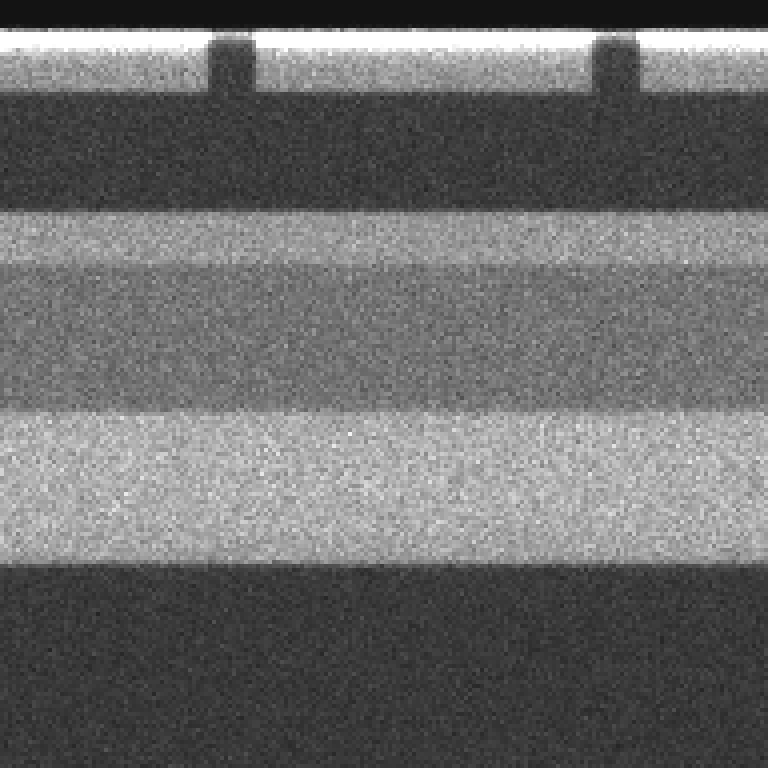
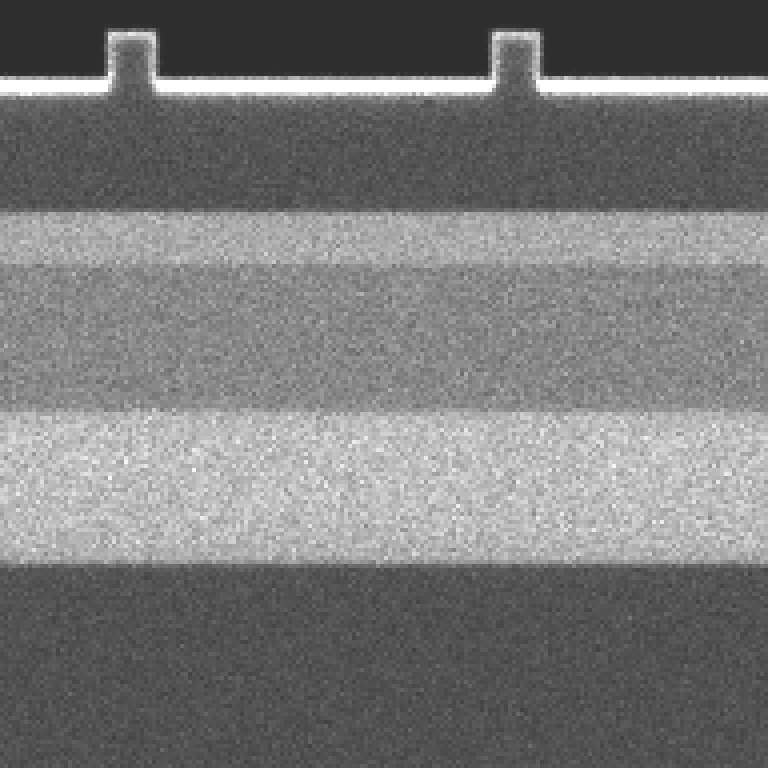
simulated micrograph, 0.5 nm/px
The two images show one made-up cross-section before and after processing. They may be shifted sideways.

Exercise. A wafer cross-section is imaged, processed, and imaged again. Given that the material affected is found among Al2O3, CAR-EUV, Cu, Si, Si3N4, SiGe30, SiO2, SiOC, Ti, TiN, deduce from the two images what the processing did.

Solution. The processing removed SiO2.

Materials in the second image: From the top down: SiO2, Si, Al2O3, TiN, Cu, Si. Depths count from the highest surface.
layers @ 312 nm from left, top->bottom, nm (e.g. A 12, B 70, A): empty 24, SiO2 6, Si 60, Al2O3 26, TiN 74, Cu 76, Si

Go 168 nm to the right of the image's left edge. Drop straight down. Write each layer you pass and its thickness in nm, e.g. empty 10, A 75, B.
empty 24, SiO2 6, Si 60, Al2O3 26, TiN 74, Cu 76, Si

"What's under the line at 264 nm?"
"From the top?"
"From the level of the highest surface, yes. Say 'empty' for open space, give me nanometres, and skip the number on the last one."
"Si 90, Al2O3 26, TiN 74, Cu 76, Si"